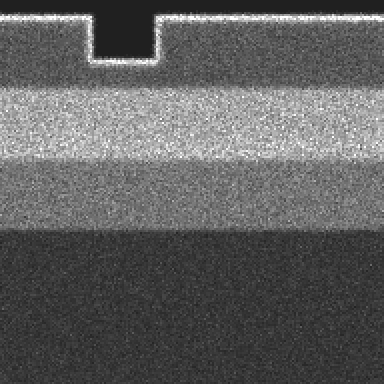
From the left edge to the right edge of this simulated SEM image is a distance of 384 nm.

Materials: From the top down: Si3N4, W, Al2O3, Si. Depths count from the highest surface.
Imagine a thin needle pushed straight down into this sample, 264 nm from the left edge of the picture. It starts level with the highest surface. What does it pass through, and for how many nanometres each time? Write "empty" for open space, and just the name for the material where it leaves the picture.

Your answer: Si3N4 72, W 72, Al2O3 70, Si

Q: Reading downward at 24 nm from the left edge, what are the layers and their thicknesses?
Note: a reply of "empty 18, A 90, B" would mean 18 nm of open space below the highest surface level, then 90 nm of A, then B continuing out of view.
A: Si3N4 72, W 72, Al2O3 70, Si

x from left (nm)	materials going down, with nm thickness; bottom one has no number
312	Si3N4 72, W 72, Al2O3 70, Si